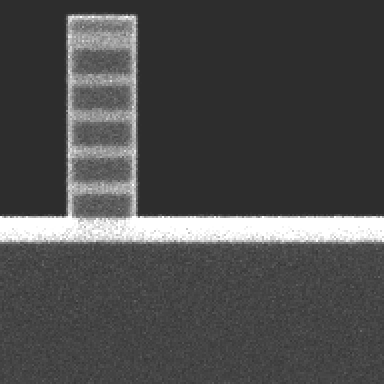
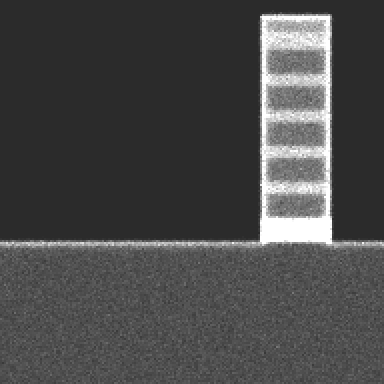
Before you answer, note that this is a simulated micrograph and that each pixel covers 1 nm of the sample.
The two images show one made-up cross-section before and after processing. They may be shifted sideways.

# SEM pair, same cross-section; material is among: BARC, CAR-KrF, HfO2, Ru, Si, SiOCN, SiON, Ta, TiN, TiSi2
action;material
removed;HfO2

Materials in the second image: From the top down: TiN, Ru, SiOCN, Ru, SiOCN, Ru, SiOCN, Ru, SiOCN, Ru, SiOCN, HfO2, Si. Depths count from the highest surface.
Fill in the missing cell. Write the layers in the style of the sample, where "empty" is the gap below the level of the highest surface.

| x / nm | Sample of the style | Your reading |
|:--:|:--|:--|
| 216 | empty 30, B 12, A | empty 226, Si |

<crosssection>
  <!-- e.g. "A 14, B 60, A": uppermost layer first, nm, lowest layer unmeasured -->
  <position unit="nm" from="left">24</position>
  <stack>empty 226, Si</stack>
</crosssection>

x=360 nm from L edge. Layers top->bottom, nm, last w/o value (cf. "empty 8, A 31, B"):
empty 226, Si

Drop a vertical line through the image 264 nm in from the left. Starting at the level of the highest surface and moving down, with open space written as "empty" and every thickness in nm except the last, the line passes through TiN 16, Ru 18, SiOCN 24, Ru 12, SiOCN 24, Ru 12, SiOCN 24, Ru 12, SiOCN 24, Ru 12, SiOCN 24, HfO2 24, Si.